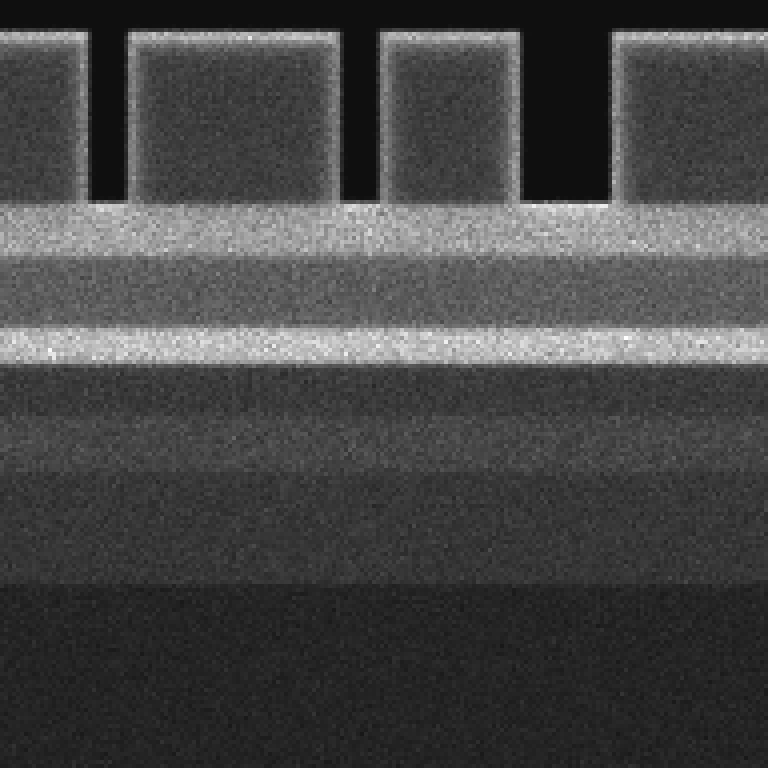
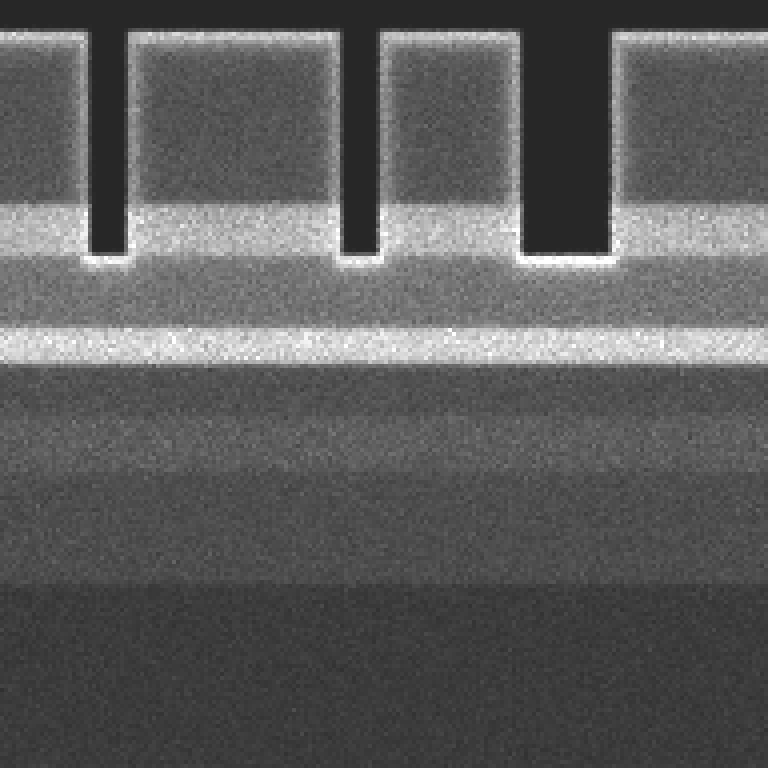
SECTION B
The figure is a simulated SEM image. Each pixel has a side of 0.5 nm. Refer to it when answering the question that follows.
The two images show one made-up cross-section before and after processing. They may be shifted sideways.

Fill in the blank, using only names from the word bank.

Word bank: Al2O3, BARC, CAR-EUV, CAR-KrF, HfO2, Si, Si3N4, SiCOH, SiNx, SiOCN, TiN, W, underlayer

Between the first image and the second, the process removed W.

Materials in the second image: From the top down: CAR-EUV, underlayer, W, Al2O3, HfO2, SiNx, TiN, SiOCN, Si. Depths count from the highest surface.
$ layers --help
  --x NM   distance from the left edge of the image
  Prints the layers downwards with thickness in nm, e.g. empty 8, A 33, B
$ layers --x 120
CAR-EUV 54, underlayer 32, W 26, Al2O3 36, HfO2 18, SiNx 26, TiN 28, SiOCN 56, Si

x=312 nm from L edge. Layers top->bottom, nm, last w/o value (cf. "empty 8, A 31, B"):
CAR-EUV 54, underlayer 32, W 26, Al2O3 36, HfO2 18, SiNx 26, TiN 28, SiOCN 56, Si